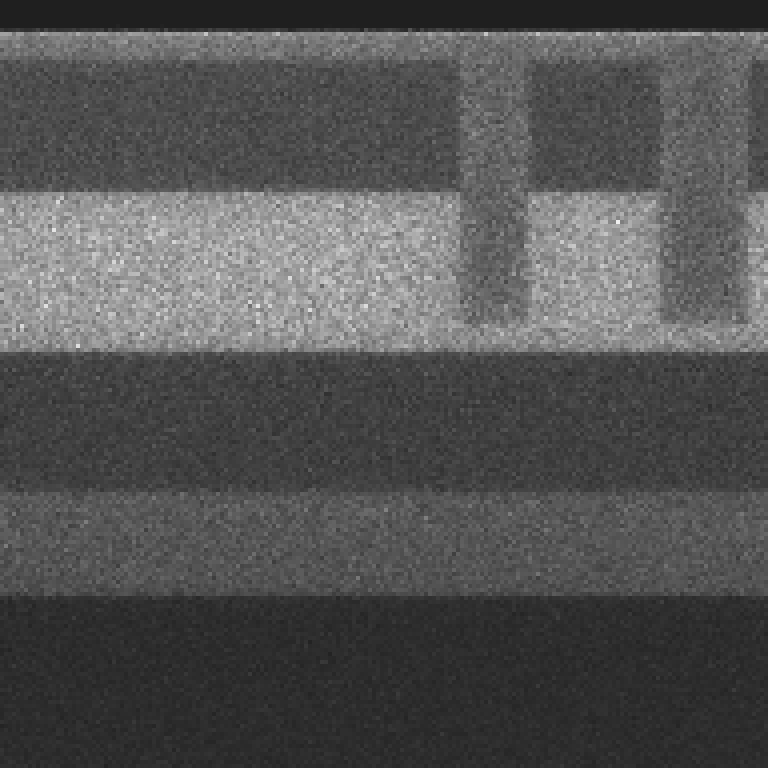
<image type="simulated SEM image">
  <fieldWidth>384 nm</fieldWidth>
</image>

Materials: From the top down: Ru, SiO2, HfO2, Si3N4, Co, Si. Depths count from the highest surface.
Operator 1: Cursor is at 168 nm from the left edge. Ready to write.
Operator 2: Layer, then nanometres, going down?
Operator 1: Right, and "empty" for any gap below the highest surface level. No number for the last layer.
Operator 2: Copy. Ru 14, SiO2 66, HfO2 80, Si3N4 70, Co 52, Si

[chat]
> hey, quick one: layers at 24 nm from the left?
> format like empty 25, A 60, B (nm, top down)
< Ru 14, SiO2 66, HfO2 80, Si3N4 70, Co 52, Si